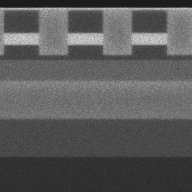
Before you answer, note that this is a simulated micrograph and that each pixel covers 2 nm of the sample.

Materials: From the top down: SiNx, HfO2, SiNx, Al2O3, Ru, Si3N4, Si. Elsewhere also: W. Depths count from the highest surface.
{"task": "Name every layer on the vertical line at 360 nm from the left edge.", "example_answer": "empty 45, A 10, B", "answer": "W 94, SiNx 10, Al2O3 42, Ru 76, Si3N4 76, Si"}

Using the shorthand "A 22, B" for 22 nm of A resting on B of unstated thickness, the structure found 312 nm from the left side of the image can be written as SiNx 50, HfO2 24, SiNx 30, Al2O3 42, Ru 76, Si3N4 76, Si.